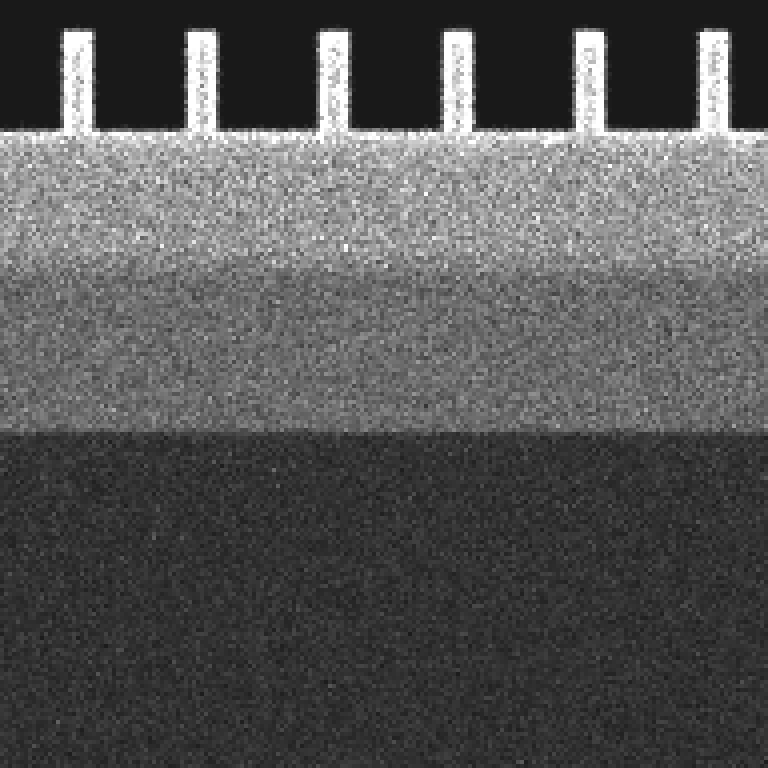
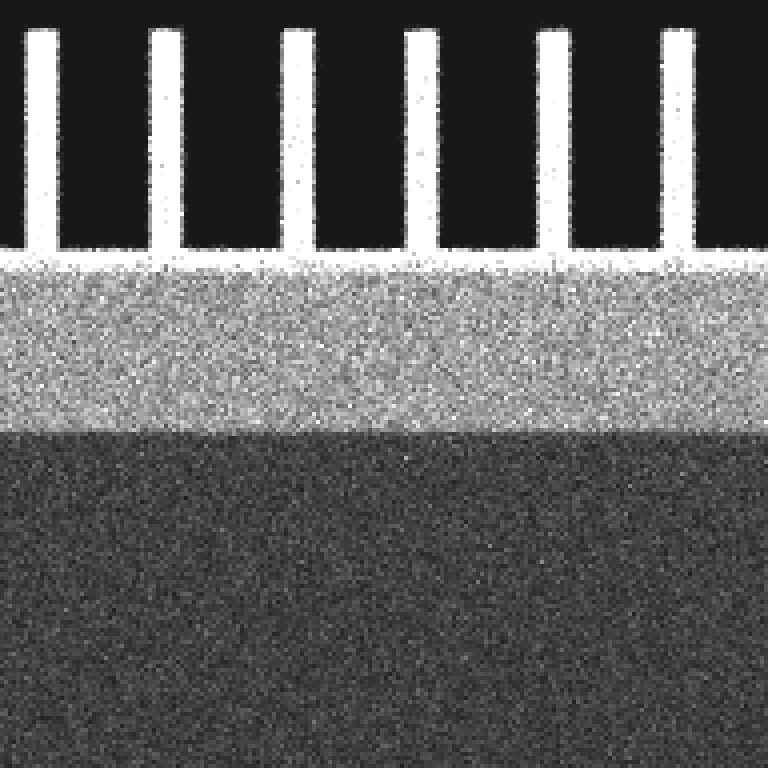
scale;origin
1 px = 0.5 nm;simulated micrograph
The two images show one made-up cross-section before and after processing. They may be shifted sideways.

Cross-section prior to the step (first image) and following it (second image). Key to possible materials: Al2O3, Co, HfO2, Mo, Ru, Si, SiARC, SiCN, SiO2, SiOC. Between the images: Ru was removed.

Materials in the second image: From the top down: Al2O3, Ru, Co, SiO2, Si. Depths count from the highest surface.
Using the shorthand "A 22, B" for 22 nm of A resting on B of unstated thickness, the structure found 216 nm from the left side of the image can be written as Al2O3 50, Ru 60, Co 10, SiO2 80, Si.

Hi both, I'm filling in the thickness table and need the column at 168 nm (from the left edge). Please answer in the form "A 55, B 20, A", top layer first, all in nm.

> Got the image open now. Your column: empty 110, Co 10, SiO2 80, Si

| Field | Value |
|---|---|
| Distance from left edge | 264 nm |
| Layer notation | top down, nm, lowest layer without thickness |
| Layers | empty 110, Co 10, SiO2 80, Si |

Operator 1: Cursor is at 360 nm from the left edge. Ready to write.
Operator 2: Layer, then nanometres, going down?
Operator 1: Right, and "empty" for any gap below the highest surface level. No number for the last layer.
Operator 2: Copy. empty 110, Co 10, SiO2 80, Si